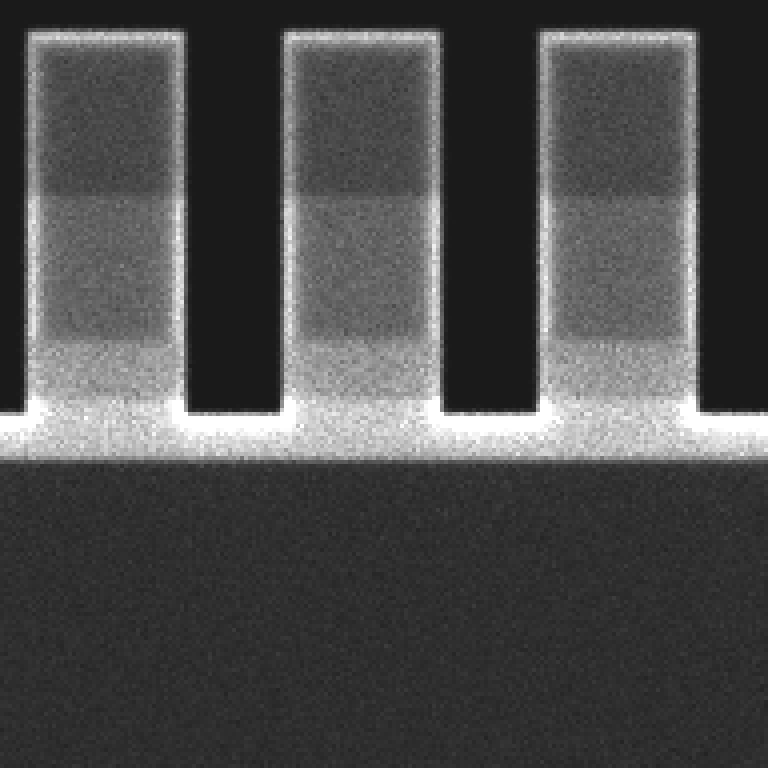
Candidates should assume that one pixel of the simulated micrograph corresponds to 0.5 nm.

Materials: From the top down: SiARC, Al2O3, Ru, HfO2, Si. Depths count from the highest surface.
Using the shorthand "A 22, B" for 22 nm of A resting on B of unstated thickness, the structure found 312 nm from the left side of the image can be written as SiARC 82, Al2O3 72, Ru 30, HfO2 30, Si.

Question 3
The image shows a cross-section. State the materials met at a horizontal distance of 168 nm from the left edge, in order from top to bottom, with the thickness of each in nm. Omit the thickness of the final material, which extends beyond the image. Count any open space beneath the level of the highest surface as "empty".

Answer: SiARC 82, Al2O3 72, Ru 30, HfO2 30, Si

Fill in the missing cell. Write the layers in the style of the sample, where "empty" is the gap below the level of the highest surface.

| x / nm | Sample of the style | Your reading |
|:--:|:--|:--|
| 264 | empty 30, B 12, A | empty 192, HfO2 22, Si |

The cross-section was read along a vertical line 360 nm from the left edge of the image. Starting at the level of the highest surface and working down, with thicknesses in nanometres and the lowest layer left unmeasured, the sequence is empty 192, HfO2 22, Si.